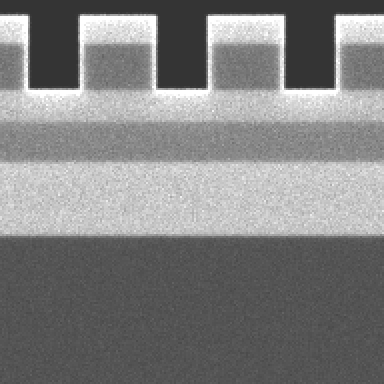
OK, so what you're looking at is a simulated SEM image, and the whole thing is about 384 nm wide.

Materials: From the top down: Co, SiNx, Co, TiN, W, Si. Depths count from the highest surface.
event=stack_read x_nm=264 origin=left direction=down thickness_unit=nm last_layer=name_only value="Co 28, SiNx 46, Co 32, TiN 40, W 74, Si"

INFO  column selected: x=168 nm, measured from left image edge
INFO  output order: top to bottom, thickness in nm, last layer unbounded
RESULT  empty 74, Co 32, TiN 40, W 74, Si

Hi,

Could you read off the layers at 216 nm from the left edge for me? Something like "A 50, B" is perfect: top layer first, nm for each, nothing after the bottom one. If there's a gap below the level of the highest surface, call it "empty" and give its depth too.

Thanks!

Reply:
Co 28, SiNx 46, Co 32, TiN 40, W 74, Si